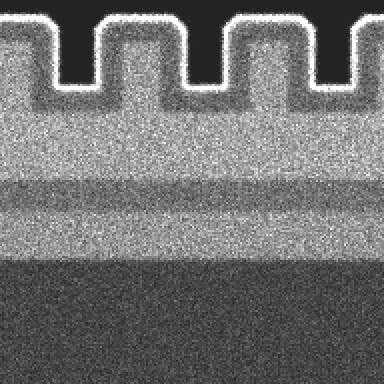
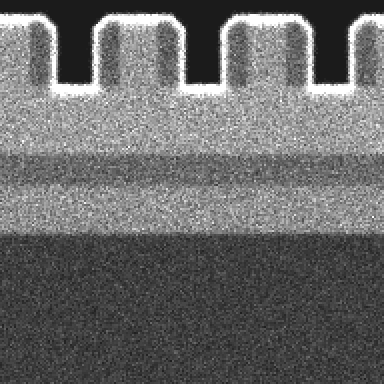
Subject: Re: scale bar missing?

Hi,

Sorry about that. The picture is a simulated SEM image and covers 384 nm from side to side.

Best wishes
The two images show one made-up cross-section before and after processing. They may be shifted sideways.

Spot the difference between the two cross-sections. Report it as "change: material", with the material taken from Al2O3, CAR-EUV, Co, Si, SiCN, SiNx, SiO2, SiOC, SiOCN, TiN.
removed: SiOCN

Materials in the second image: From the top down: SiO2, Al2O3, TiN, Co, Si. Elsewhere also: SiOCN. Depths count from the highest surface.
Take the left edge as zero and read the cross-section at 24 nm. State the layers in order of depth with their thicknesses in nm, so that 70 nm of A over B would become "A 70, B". SiO2 70, Al2O3 68, TiN 32, Co 48, Si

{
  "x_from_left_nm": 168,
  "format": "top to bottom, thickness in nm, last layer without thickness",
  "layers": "SiOCN 70, Al2O3 68, TiN 32, Co 48, Si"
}